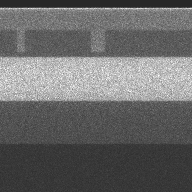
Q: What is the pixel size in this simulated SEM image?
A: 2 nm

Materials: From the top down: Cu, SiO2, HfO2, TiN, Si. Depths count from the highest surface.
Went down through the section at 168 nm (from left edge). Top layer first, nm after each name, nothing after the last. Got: Cu 44, SiO2 54, HfO2 88, TiN 86, Si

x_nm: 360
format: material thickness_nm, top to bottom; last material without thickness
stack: Cu 44, SiO2 54, HfO2 88, TiN 86, Si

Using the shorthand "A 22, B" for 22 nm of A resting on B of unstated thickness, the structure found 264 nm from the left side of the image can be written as Cu 44, SiO2 54, HfO2 88, TiN 86, Si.